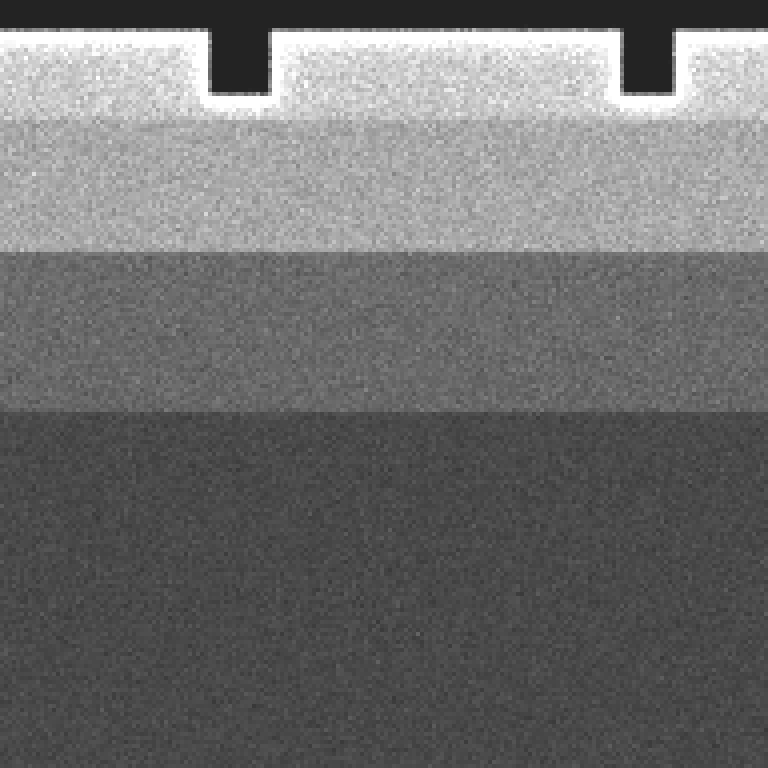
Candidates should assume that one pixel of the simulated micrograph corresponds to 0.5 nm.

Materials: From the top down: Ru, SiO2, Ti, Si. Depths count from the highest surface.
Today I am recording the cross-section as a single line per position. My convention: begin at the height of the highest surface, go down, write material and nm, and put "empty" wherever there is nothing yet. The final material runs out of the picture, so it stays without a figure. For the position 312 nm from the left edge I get empty 32, Ru 12, SiO2 66, Ti 80, Si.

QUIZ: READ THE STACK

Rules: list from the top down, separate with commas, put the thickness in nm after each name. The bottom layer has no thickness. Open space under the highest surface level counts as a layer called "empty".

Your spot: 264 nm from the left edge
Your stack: Ru 44, SiO2 66, Ti 80, Si